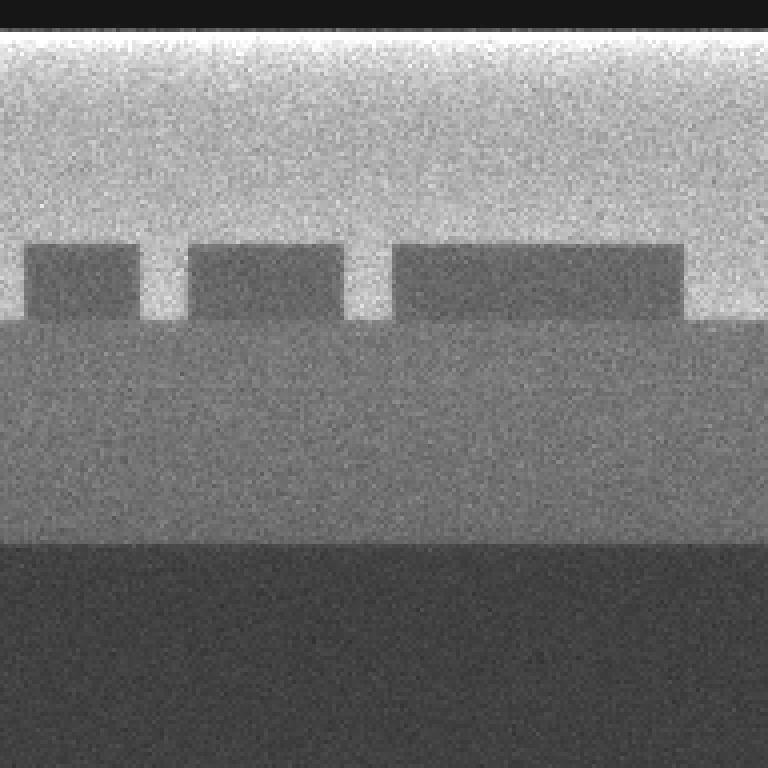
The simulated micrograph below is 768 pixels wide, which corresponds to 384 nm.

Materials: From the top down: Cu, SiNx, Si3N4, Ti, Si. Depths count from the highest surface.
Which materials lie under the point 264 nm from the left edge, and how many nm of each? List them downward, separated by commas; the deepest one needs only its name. Cu 106, SiNx 38, Si3N4 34, Ti 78, Si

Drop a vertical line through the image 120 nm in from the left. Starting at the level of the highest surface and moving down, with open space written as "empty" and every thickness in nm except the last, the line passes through Cu 106, SiNx 38, Si3N4 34, Ti 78, Si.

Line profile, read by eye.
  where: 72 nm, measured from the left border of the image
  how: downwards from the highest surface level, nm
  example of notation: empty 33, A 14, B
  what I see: Cu 144, Si3N4 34, Ti 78, Si